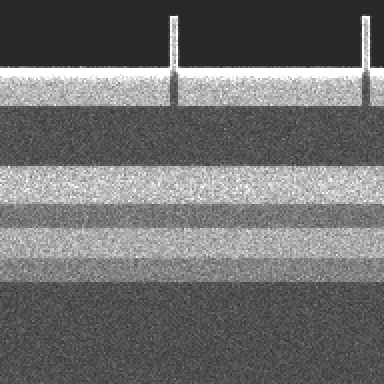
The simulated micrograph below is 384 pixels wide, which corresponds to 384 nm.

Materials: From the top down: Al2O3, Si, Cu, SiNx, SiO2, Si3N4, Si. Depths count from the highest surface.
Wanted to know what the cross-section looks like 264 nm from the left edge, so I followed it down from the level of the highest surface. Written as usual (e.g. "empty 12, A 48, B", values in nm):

empty 52, Al2O3 38, Si 60, Cu 38, SiNx 24, SiO2 30, Si3N4 24, Si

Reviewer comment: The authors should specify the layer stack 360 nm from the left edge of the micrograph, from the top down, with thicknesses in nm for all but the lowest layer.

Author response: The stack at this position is empty 52, Al2O3 38, Si 60, Cu 38, SiNx 24, SiO2 30, Si3N4 24, Si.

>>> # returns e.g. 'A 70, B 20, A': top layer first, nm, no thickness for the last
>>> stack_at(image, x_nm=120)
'empty 52, Al2O3 38, Si 60, Cu 38, SiNx 24, SiO2 30, Si3N4 24, Si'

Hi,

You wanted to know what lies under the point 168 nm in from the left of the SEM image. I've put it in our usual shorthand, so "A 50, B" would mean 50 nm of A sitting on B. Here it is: empty 52, Al2O3 38, Si 60, Cu 38, SiNx 24, SiO2 30, Si3N4 24, Si